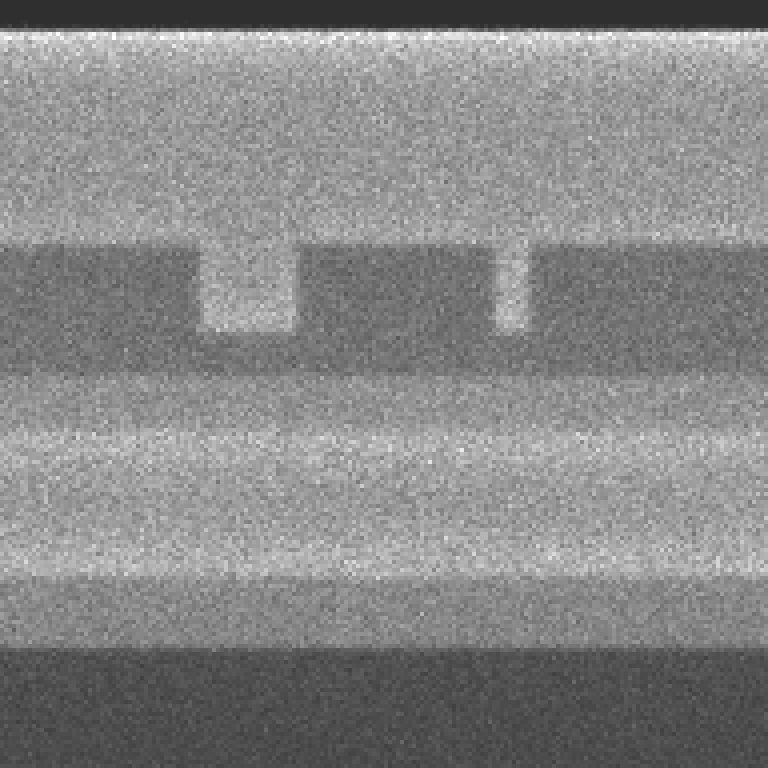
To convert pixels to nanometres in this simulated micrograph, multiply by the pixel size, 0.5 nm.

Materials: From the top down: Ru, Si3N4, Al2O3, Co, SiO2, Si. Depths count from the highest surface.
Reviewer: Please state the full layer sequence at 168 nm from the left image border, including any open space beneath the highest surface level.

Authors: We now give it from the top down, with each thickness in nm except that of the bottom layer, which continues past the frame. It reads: Ru 106, Si3N4 66, Al2O3 28, Co 72, SiO2 36, Si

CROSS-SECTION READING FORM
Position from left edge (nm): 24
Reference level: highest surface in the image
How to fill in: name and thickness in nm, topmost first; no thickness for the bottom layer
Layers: Ru 106, Si3N4 66, Al2O3 28, Co 72, SiO2 36, Si